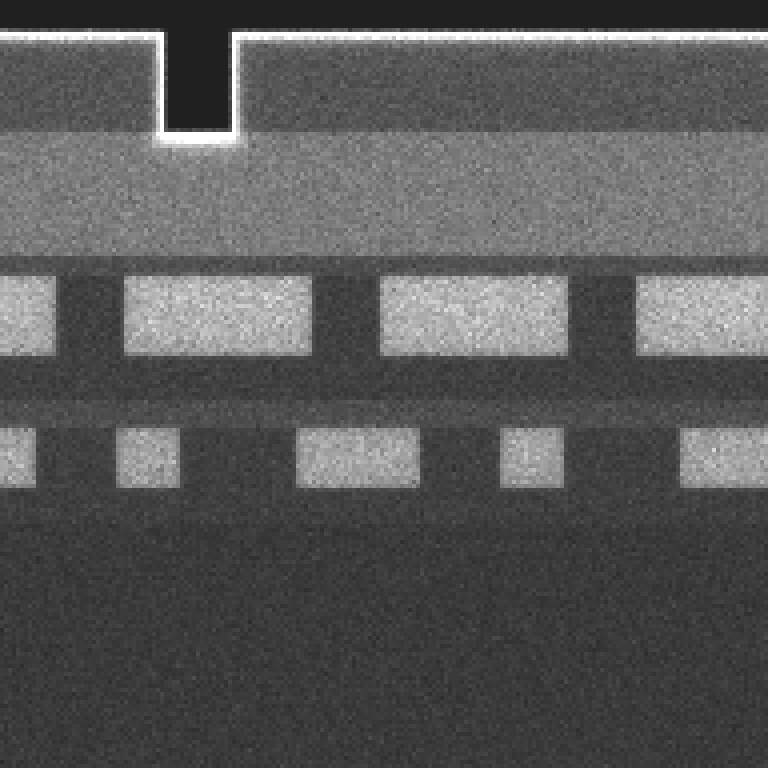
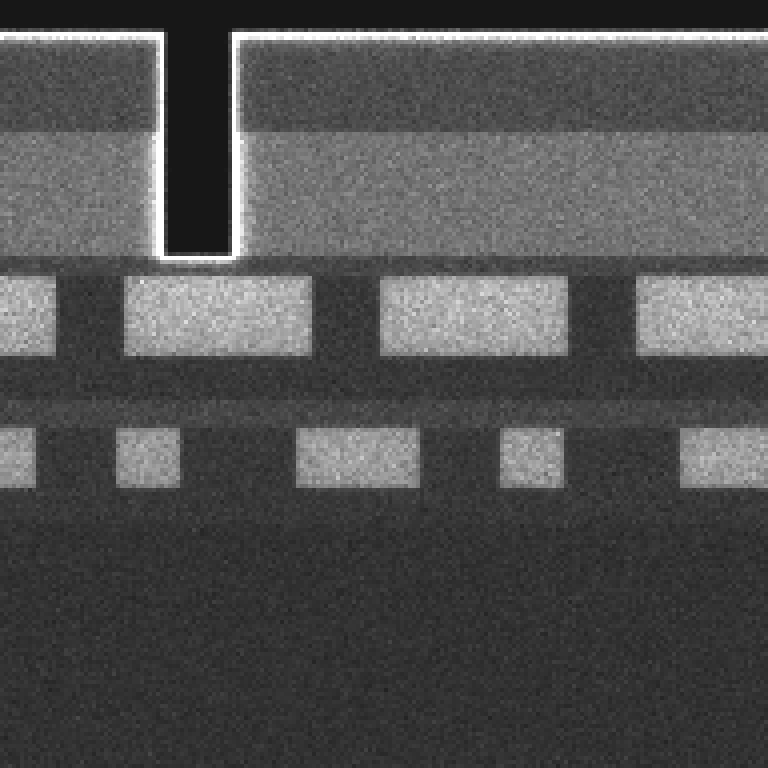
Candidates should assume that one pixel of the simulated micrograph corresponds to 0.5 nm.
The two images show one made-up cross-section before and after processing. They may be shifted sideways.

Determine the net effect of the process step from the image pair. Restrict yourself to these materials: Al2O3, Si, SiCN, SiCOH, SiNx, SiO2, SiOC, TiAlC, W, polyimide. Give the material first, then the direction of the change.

SiO2: removed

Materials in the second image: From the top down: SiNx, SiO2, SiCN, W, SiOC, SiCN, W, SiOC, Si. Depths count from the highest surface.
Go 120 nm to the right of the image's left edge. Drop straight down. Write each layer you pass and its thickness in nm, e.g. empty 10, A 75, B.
SiNx 50, SiO2 62, SiCN 10, W 40, SiOC 22, SiCN 14, SiOC 48, Si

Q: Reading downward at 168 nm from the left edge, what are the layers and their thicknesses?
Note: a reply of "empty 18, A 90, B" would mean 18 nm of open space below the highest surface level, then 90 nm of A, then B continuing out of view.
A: SiNx 50, SiO2 62, SiCN 10, SiOC 62, SiCN 14, W 30, SiOC 18, Si